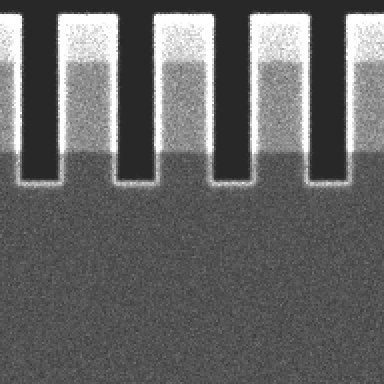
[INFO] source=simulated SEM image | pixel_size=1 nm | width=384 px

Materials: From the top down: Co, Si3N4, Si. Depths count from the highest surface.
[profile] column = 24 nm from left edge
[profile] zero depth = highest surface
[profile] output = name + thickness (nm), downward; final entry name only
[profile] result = empty 166, Si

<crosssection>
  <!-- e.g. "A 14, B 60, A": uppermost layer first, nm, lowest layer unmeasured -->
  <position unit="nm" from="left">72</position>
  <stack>Co 46, Si3N4 90, Si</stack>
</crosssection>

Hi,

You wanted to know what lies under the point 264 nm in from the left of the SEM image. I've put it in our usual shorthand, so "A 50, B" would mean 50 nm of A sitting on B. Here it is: Co 46, Si3N4 90, Si